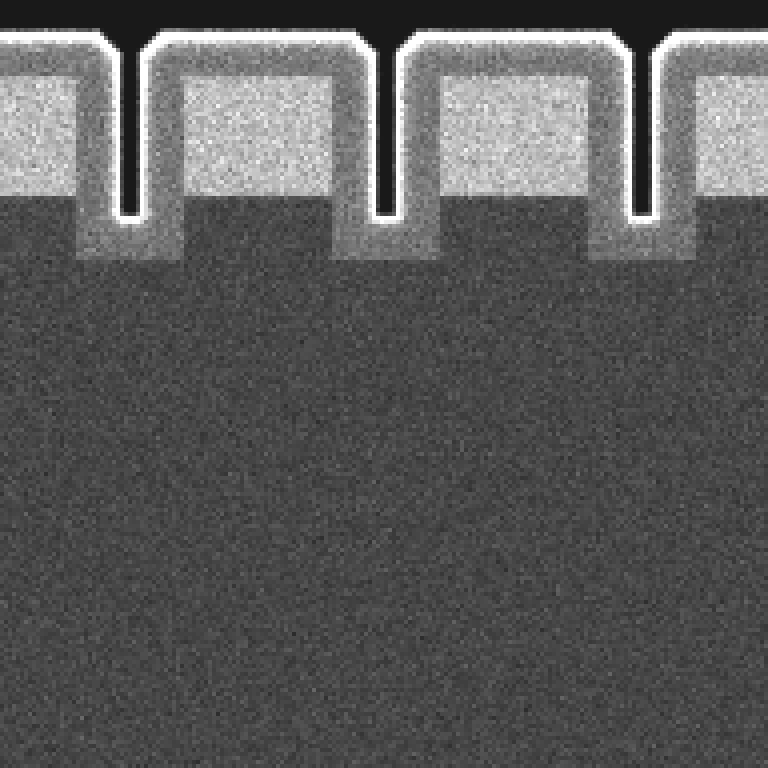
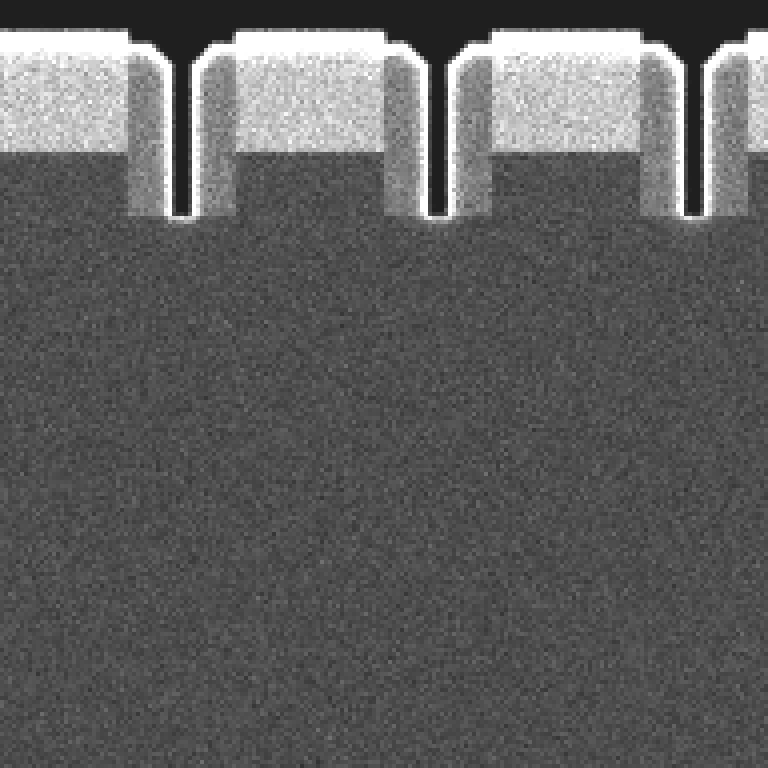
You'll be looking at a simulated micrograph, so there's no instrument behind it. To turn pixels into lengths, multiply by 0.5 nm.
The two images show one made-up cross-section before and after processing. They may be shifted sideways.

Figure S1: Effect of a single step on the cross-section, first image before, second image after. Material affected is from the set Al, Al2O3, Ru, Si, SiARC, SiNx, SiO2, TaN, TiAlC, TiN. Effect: removed SiNx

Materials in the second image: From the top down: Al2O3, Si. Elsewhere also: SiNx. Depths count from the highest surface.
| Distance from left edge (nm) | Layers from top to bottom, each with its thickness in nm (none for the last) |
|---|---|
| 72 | empty 6, SiNx 86, Si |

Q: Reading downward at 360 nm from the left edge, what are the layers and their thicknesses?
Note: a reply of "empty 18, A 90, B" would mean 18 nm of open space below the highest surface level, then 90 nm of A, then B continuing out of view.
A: empty 8, SiNx 84, Si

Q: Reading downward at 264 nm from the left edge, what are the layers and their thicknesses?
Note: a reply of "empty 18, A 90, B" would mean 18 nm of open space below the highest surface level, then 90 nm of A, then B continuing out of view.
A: Al2O3 60, Si